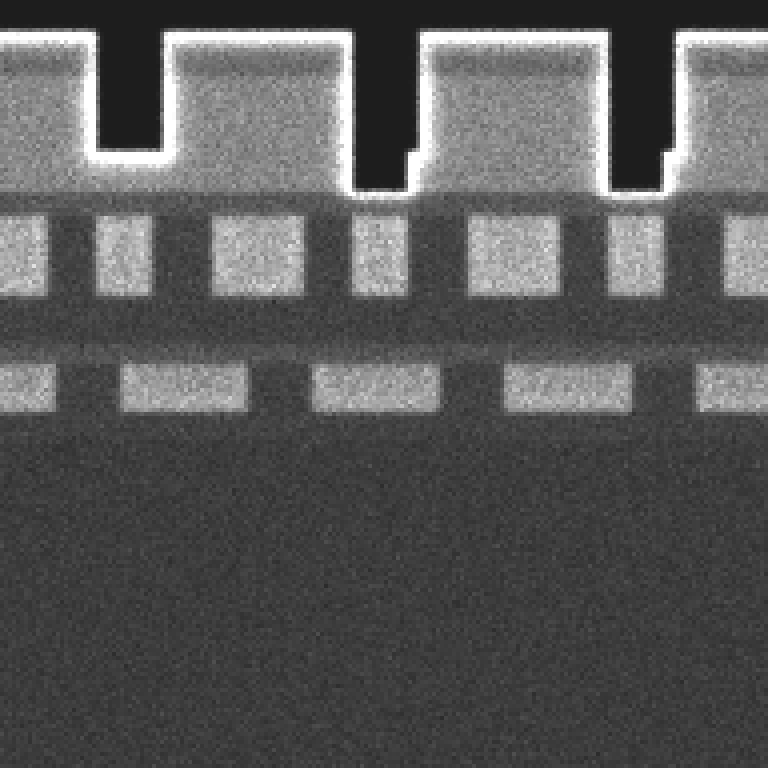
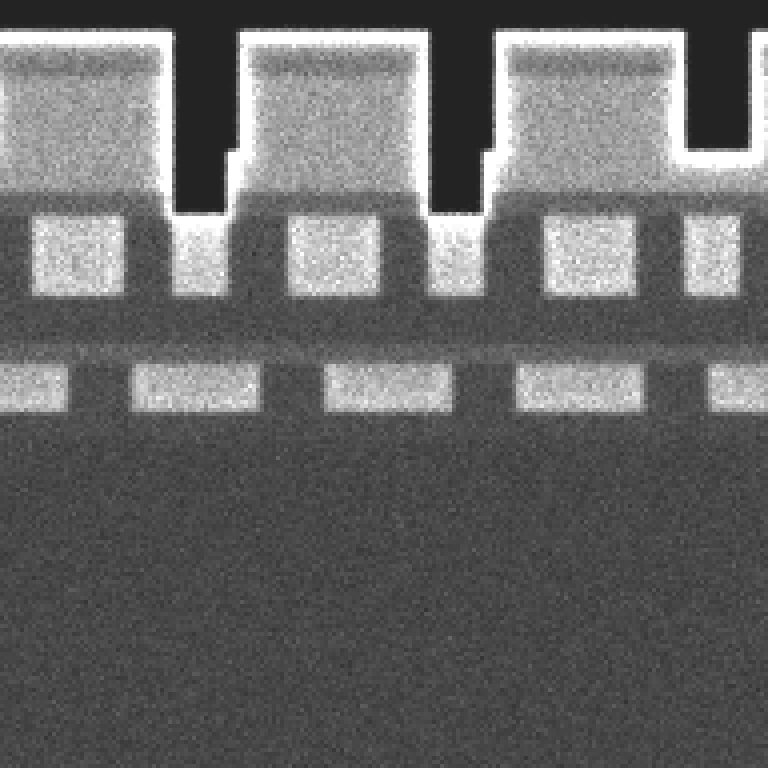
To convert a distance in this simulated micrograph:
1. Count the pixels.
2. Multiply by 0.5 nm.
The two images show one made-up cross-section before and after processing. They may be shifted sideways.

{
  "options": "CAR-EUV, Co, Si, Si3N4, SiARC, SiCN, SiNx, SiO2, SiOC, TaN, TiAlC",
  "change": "removed",
  "material": "SiCN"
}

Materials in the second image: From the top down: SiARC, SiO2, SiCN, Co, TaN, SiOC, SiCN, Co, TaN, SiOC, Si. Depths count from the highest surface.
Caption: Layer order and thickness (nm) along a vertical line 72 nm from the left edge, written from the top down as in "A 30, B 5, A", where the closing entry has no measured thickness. SiARC 22, SiO2 58, SiCN 12, SiOC 64, SiCN 10, TaN 24, SiOC 14, Si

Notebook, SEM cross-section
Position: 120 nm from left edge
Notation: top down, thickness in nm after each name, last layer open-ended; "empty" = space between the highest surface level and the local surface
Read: SiARC 22, SiO2 58, SiCN 12, SiOC 64, SiCN 10, Co 16, TaN 8, SiOC 14, Si